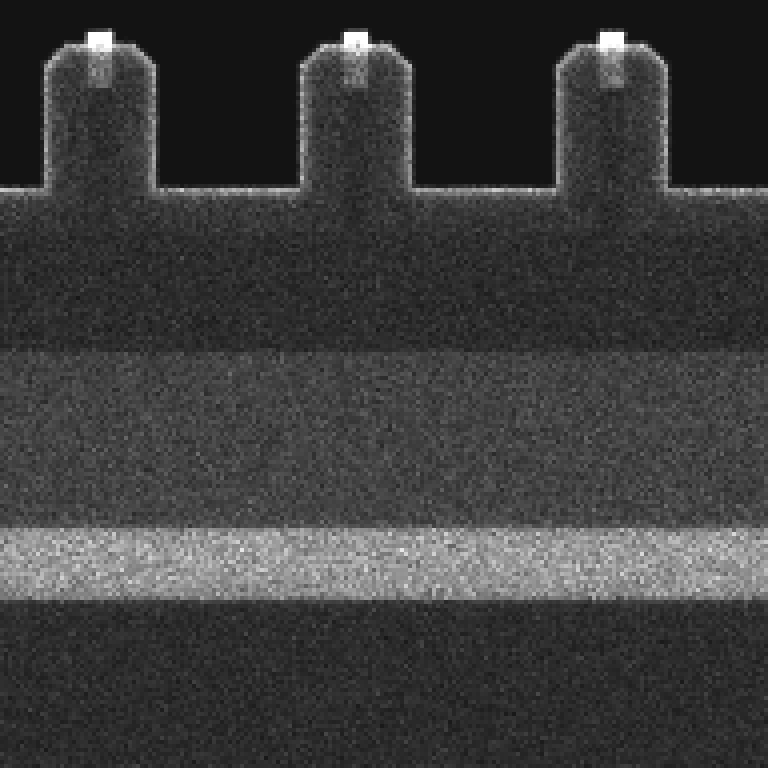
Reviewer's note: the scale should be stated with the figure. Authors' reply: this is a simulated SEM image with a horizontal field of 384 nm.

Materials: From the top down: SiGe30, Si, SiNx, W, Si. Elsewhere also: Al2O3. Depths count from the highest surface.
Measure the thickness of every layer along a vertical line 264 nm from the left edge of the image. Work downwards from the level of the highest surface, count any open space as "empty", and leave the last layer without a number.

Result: empty 78, SiGe30 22, Si 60, SiNx 88, W 36, Si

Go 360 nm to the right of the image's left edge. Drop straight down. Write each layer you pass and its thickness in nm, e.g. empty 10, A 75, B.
empty 78, SiGe30 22, Si 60, SiNx 88, W 36, Si